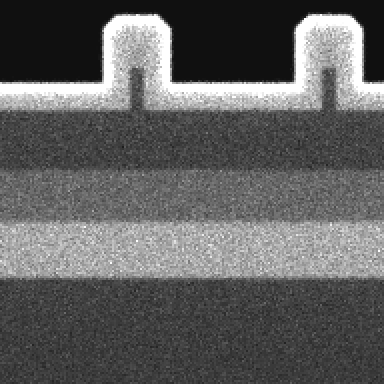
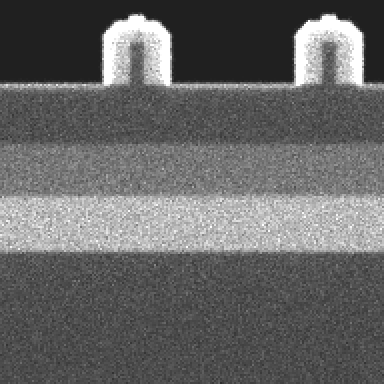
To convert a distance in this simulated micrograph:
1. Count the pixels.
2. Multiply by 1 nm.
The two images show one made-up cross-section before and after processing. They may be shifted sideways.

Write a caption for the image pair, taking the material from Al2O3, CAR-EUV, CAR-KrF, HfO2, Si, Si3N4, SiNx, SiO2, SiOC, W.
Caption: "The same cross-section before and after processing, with Al2O3 removed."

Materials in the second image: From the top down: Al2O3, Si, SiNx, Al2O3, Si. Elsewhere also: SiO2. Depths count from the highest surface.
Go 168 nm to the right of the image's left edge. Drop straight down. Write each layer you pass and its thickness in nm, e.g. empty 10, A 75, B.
empty 18, Al2O3 50, Si 60, SiNx 52, Al2O3 56, Si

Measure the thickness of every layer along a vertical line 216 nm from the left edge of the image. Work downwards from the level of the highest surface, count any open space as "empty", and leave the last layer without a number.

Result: empty 68, Si 60, SiNx 52, Al2O3 56, Si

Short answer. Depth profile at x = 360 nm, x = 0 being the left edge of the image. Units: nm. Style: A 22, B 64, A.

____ empty 18, Al2O3 50, Si 60, SiNx 52, Al2O3 56, Si